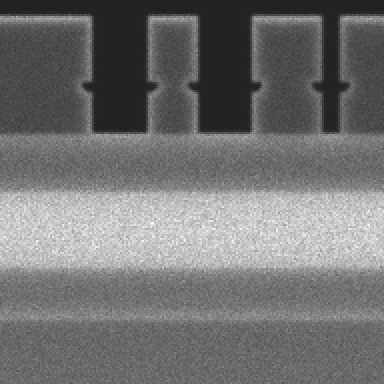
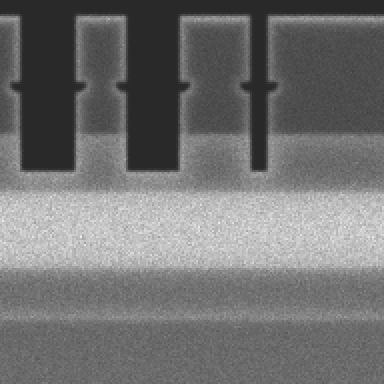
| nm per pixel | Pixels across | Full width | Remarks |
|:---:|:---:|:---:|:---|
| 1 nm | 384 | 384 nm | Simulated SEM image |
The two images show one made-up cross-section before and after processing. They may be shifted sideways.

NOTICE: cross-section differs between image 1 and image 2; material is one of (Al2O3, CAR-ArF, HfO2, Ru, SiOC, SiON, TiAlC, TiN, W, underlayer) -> removed: Ru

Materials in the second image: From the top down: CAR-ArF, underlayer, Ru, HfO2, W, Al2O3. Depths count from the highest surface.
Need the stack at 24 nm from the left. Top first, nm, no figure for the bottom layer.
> empty 156, Ru 20, HfO2 76, W 52, Al2O3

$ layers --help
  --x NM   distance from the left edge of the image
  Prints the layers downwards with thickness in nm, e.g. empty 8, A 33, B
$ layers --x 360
CAR-ArF 66, underlayer 52, Ru 58, HfO2 76, W 52, Al2O3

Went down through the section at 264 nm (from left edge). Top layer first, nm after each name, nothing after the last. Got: empty 156, Ru 20, HfO2 76, W 52, Al2O3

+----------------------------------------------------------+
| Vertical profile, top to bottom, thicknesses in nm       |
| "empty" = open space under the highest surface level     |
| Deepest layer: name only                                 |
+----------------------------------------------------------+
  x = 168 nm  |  empty 156, Ru 20, HfO2 76, W 52, Al2O3